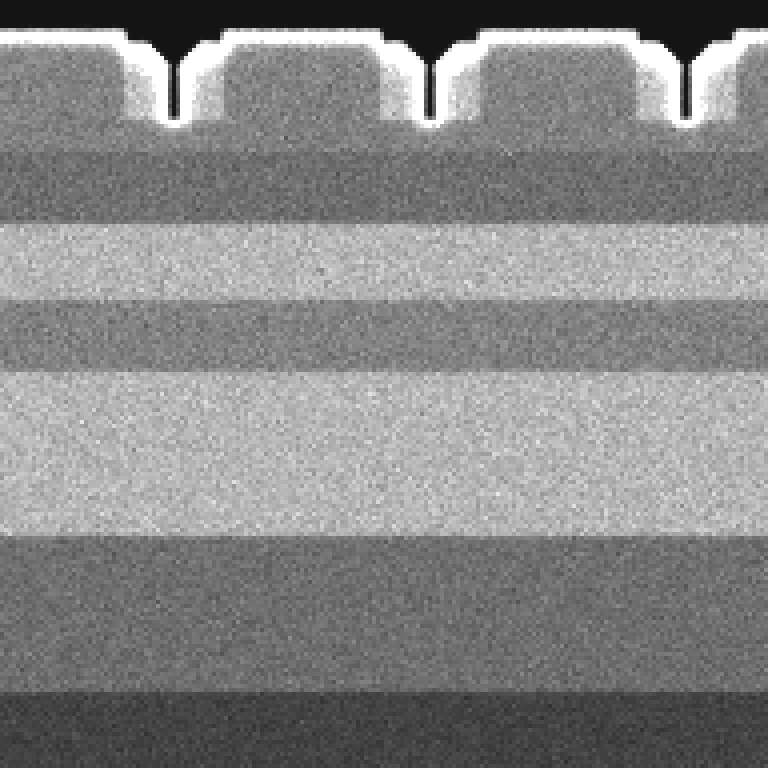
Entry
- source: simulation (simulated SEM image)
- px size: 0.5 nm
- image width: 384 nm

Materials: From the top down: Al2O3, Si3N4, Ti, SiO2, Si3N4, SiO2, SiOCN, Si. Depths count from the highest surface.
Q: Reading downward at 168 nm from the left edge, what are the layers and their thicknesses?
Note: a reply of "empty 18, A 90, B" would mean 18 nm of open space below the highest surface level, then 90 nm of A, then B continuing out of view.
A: Si3N4 60, Ti 36, SiO2 38, Si3N4 36, SiO2 82, SiOCN 78, Si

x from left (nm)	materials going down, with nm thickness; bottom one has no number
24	Si3N4 60, Ti 36, SiO2 38, Si3N4 36, SiO2 82, SiOCN 78, Si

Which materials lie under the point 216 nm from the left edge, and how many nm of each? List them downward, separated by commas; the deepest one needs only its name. empty 44, Si3N4 16, Ti 36, SiO2 38, Si3N4 36, SiO2 82, SiOCN 78, Si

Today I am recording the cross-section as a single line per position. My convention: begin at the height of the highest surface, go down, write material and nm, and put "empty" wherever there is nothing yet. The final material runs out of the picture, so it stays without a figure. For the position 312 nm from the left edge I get Si3N4 60, Ti 36, SiO2 38, Si3N4 36, SiO2 82, SiOCN 78, Si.